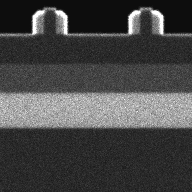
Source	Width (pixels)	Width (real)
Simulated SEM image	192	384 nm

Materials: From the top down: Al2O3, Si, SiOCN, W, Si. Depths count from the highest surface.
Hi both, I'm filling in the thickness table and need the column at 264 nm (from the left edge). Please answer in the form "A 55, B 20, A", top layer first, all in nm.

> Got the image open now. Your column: empty 10, Al2O3 42, Si 60, SiOCN 58, W 70, Si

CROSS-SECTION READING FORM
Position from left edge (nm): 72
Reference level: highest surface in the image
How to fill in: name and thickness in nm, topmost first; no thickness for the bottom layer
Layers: empty 10, Al2O3 42, Si 60, SiOCN 58, W 70, Si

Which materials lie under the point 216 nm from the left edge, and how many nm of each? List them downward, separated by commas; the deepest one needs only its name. empty 52, Si 60, SiOCN 58, W 70, Si